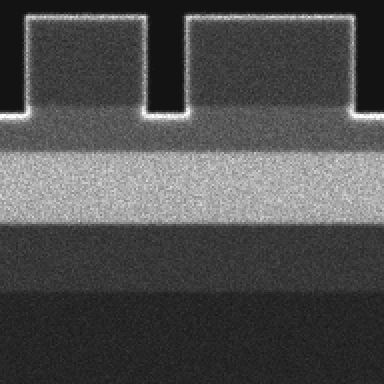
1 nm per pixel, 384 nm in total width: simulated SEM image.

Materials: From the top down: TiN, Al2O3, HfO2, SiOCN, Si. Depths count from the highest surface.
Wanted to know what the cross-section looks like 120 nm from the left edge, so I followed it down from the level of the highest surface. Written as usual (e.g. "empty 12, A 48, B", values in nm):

TiN 90, Al2O3 46, HfO2 72, SiOCN 68, Si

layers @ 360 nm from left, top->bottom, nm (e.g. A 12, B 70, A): empty 98, Al2O3 38, HfO2 72, SiOCN 68, Si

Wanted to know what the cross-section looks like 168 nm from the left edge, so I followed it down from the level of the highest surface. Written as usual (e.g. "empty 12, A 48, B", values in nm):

empty 98, Al2O3 38, HfO2 72, SiOCN 68, Si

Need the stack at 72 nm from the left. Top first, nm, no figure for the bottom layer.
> TiN 90, Al2O3 46, HfO2 72, SiOCN 68, Si